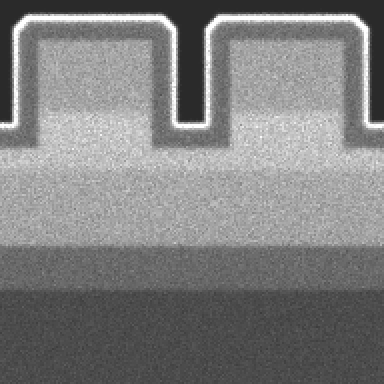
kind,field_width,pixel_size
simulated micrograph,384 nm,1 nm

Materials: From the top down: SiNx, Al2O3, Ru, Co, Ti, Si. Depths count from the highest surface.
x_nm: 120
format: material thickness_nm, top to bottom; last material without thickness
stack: SiNx 24, Al2O3 72, Ru 58, Co 76, Ti 44, Si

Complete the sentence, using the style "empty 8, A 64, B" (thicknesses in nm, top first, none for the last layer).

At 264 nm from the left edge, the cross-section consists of SiNx 24, Al2O3 72, Ru 58, Co 76, Ti 44, Si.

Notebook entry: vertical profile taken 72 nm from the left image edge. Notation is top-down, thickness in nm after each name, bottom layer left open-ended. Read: SiNx 24, Al2O3 72, Ru 58, Co 76, Ti 44, Si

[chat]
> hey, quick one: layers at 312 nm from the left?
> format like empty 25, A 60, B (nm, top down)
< SiNx 24, Al2O3 72, Ru 58, Co 76, Ti 44, Si